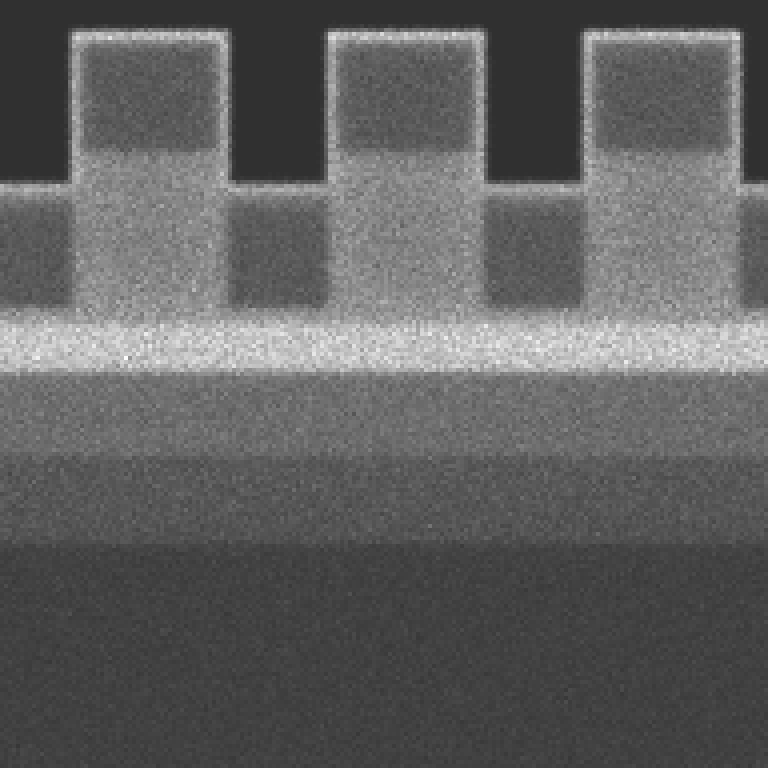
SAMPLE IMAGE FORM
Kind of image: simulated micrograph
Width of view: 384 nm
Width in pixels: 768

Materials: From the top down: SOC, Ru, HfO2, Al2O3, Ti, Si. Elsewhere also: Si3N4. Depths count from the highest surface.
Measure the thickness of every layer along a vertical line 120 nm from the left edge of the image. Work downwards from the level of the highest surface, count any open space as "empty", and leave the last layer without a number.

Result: empty 76, SOC 62, Ru 8, HfO2 24, Al2O3 42, Ti 44, Si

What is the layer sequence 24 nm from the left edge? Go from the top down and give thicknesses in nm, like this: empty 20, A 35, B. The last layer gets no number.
empty 76, SOC 62, Ru 8, HfO2 24, Al2O3 42, Ti 44, Si